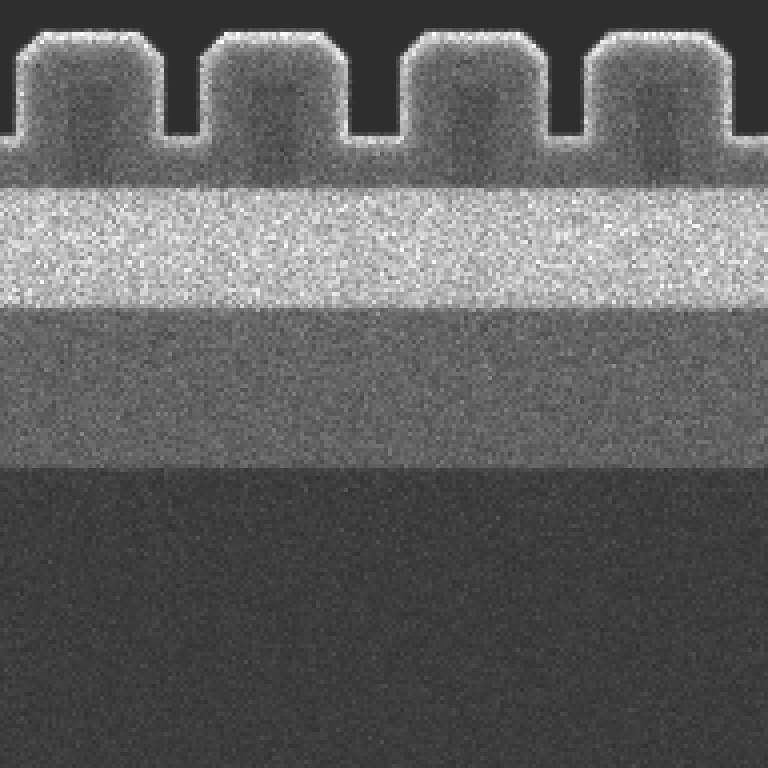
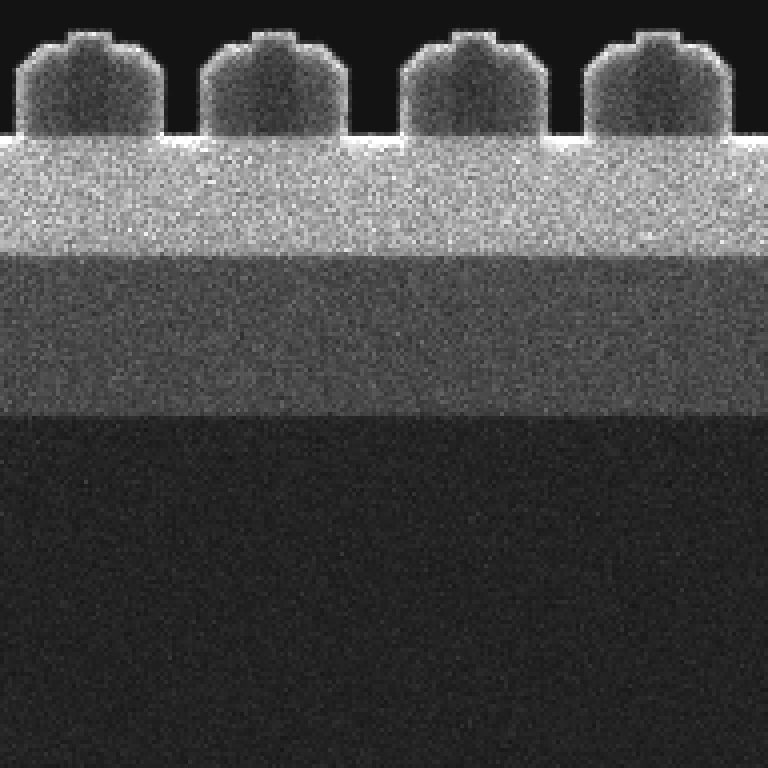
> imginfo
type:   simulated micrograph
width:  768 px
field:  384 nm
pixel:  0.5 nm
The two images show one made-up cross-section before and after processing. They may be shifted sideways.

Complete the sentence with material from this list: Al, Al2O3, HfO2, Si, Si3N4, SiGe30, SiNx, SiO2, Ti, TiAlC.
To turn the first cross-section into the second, SiO2 must be removed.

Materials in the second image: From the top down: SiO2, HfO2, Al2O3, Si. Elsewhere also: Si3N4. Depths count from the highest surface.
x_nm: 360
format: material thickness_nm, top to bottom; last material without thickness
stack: empty 14, SiO2 38, HfO2 60, Al2O3 80, Si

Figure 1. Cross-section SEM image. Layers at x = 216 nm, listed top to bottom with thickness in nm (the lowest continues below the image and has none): empty 6, SiO2 46, HfO2 60, Al2O3 80, Si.